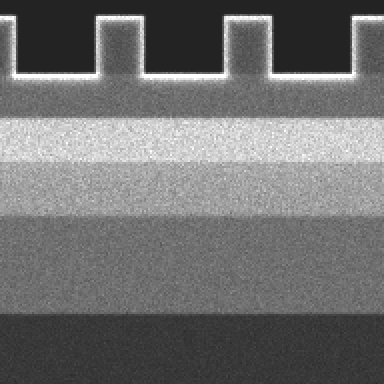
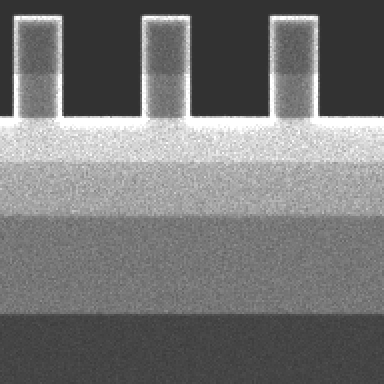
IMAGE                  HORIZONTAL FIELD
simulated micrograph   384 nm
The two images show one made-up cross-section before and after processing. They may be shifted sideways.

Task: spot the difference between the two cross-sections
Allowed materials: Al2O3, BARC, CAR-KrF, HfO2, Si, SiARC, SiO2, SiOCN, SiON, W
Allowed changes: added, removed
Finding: removed SiO2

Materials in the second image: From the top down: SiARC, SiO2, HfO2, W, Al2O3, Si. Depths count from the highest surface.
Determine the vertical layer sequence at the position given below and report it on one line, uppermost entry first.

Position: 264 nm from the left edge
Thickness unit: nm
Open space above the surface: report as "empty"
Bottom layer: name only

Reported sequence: empty 102, HfO2 44, W 54, Al2O3 98, Si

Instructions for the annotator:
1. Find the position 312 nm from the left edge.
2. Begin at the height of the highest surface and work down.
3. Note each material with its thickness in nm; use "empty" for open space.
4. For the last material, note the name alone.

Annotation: SiARC 58, SiO2 44, HfO2 44, W 54, Al2O3 98, Si